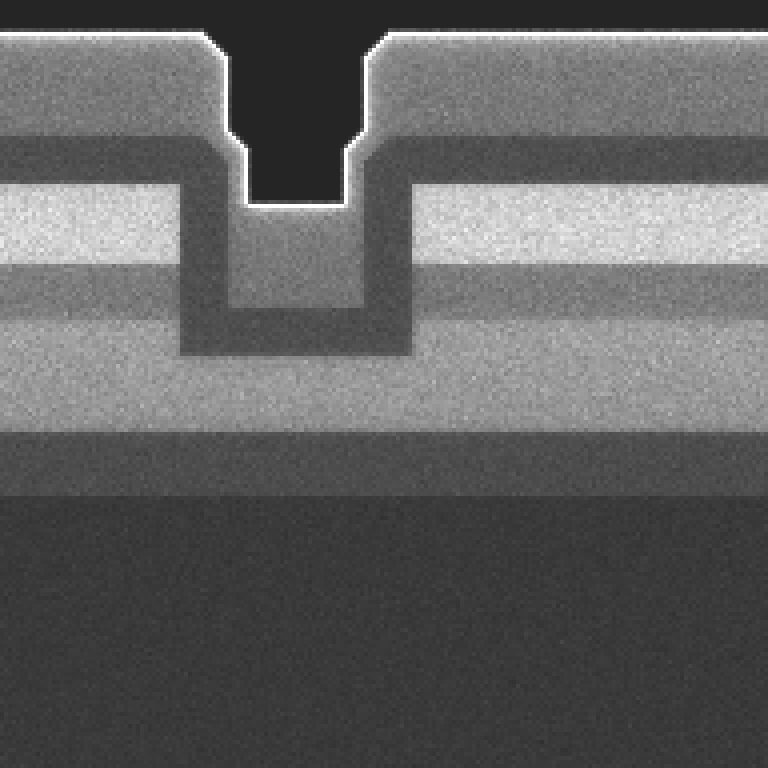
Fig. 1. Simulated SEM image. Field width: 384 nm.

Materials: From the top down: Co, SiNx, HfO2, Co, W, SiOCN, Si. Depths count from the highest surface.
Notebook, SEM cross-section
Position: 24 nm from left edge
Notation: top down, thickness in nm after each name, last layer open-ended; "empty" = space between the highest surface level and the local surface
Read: Co 52, SiNx 24, HfO2 40, Co 28, W 56, SiOCN 32, Si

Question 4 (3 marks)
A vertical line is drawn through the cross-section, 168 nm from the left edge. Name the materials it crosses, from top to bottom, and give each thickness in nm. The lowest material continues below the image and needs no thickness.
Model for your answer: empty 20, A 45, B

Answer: empty 86, Co 52, SiNx 24, W 38, SiOCN 32, Si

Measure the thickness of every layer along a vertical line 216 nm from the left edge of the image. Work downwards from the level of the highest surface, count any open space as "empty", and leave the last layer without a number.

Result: Co 52, SiNx 24, HfO2 40, Co 28, W 56, SiOCN 32, Si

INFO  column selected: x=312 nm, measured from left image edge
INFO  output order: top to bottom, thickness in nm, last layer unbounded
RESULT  Co 52, SiNx 24, HfO2 40, Co 28, W 56, SiOCN 32, Si